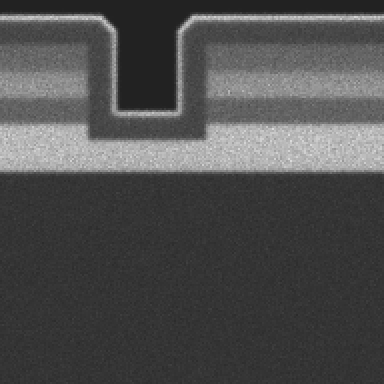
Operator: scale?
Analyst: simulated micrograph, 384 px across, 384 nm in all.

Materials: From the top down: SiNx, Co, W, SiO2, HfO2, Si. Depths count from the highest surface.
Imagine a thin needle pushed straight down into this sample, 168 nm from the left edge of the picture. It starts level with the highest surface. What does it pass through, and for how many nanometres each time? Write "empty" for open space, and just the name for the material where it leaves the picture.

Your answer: empty 96, SiNx 28, HfO2 32, Si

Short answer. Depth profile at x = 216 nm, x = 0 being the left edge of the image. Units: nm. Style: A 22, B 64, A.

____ SiNx 28, Co 28, W 26, SiO2 26, HfO2 48, Si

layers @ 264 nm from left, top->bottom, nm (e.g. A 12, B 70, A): SiNx 28, Co 28, W 26, SiO2 26, HfO2 48, Si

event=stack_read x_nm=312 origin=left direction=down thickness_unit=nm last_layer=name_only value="SiNx 28, Co 28, W 26, SiO2 26, HfO2 48, Si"